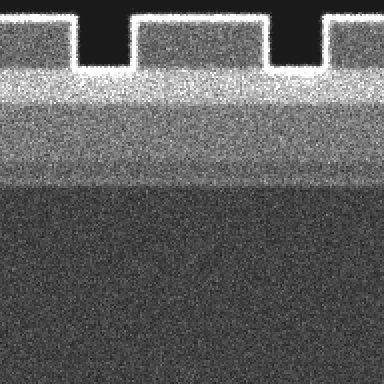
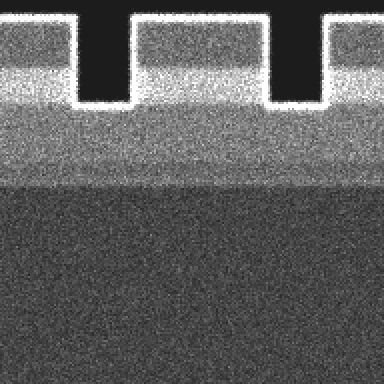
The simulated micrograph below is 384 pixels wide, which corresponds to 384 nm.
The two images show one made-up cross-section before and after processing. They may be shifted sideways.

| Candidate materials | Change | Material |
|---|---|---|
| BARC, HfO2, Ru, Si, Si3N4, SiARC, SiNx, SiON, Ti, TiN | removed | Ru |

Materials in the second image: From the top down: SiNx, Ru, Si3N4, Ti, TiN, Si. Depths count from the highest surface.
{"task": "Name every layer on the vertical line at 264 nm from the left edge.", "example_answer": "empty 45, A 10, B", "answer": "SiNx 52, Ru 36, Si3N4 58, Ti 16, TiN 8, Si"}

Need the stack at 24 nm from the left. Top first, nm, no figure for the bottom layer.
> SiNx 52, Ru 36, Si3N4 58, Ti 16, TiN 8, Si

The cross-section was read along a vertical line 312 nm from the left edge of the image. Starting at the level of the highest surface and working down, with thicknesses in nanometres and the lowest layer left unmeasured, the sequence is empty 88, Si3N4 58, Ti 16, TiN 8, Si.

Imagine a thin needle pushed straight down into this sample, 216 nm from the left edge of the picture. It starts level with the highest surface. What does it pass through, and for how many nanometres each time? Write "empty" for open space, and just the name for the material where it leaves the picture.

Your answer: SiNx 52, Ru 36, Si3N4 58, Ti 16, TiN 8, Si